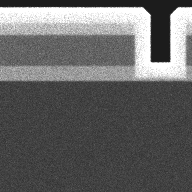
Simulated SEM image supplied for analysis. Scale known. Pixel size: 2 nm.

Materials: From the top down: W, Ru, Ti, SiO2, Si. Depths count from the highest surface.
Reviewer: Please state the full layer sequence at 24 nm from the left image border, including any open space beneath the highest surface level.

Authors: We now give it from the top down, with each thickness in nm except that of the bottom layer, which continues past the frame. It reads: W 30, Ru 24, Ti 62, SiO2 30, Si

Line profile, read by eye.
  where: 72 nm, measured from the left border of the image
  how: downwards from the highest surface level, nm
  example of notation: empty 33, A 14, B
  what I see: W 30, Ru 24, Ti 62, SiO2 30, Si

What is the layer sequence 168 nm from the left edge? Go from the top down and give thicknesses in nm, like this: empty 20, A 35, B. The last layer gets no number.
W 30, Ru 24, Ti 62, SiO2 30, Si